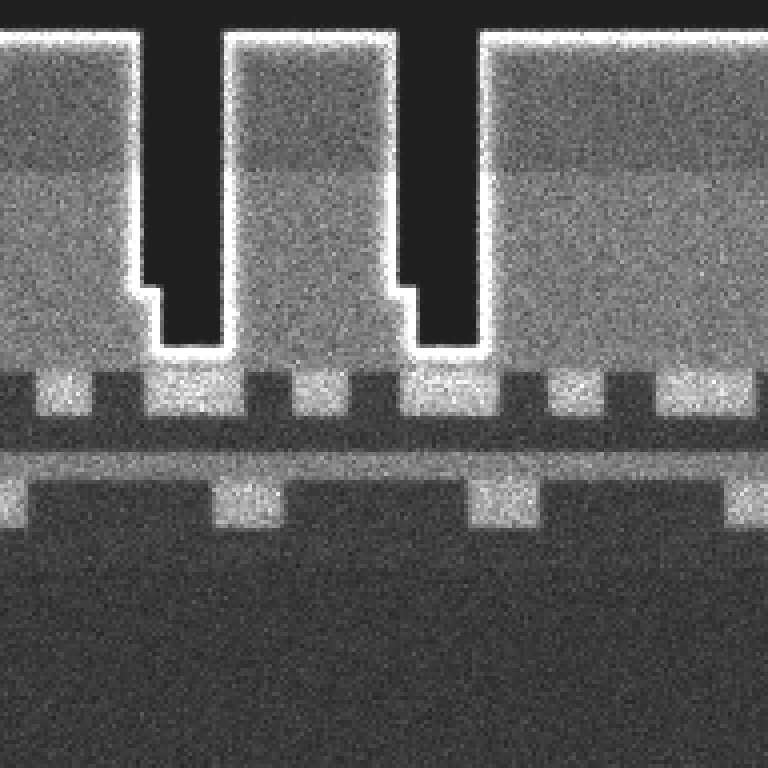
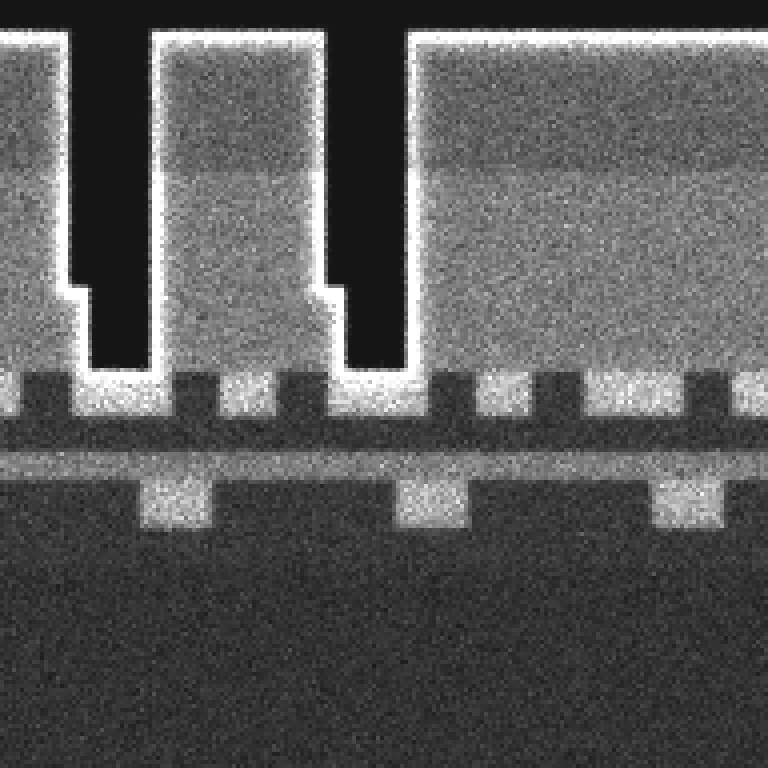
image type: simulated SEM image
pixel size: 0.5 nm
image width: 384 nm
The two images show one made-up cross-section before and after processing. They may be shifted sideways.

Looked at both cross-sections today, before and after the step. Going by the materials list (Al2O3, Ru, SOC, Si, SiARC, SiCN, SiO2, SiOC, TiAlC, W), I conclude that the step removed Al2O3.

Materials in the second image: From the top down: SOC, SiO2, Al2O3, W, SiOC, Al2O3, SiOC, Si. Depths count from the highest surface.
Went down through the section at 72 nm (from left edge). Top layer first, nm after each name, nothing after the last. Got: empty 170, W 22, SiOC 18, Al2O3 14, W 24, SiOC 20, Si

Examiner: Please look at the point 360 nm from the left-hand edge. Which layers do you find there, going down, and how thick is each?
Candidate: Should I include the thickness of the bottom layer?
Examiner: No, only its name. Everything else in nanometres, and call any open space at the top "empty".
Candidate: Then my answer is SOC 70, SiO2 88, Al2O3 12, SiOC 40, Al2O3 14, W 24, SiOC 20, Si